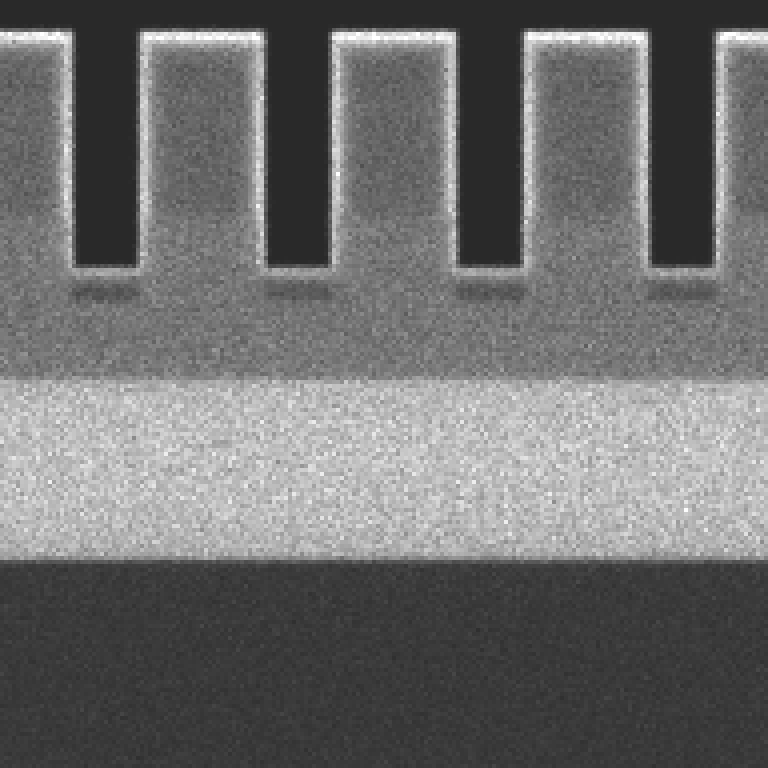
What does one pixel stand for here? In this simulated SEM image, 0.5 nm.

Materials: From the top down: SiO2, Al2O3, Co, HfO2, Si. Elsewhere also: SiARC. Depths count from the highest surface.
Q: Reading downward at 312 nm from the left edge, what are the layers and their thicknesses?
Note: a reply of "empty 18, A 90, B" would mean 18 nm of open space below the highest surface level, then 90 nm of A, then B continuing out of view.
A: SiO2 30, Al2O3 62, Co 82, HfO2 90, Si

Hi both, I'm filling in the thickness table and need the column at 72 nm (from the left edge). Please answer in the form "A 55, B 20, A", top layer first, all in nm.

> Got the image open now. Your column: SiO2 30, Al2O3 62, Co 82, HfO2 90, Si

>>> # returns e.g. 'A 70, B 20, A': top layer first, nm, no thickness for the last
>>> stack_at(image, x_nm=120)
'SiO2 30, Al2O3 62, Co 82, HfO2 90, Si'